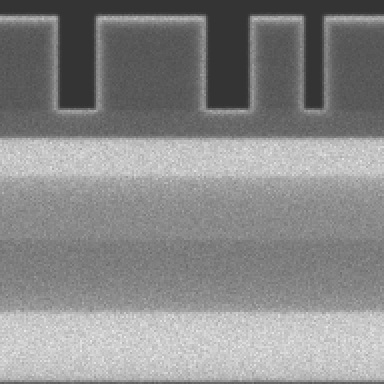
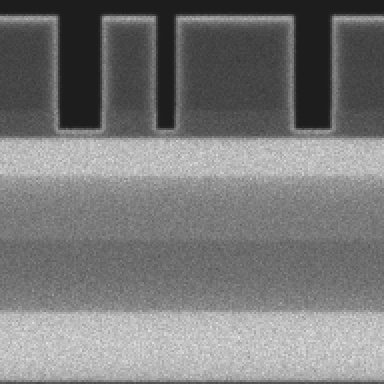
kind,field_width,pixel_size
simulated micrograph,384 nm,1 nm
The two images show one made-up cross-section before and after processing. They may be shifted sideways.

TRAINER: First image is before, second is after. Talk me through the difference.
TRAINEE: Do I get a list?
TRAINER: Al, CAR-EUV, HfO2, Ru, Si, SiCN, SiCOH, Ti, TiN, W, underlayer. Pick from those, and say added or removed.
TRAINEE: removed: TiN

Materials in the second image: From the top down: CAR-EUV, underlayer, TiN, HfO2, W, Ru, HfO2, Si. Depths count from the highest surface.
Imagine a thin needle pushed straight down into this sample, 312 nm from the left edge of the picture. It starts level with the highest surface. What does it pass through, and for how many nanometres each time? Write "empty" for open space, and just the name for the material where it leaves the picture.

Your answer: empty 114, TiN 8, HfO2 38, W 64, Ru 72, HfO2 70, Si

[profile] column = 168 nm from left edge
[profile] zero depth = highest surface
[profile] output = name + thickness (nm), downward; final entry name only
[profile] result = empty 114, TiN 8, HfO2 38, W 64, Ru 72, HfO2 70, Si